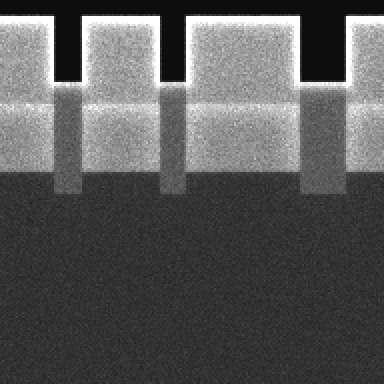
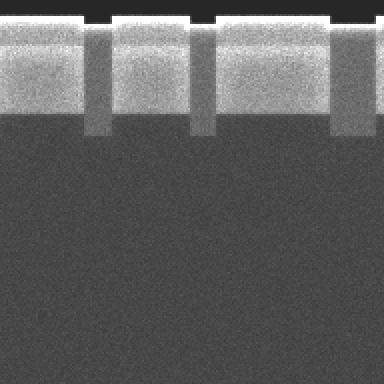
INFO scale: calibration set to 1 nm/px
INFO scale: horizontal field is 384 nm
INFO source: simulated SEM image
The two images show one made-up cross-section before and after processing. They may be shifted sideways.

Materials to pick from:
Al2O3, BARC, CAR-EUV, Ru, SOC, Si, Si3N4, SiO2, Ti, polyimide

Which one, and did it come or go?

Al2O3 - removed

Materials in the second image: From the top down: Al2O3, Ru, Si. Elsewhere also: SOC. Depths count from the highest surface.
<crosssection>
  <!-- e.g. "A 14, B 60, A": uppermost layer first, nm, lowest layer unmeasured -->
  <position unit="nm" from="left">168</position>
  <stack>Al2O3 30, Ru 68, Si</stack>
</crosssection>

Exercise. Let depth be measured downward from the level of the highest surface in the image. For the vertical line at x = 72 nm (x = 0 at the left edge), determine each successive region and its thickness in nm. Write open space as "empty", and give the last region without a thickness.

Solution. Al2O3 30, Ru 68, Si